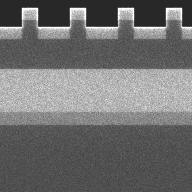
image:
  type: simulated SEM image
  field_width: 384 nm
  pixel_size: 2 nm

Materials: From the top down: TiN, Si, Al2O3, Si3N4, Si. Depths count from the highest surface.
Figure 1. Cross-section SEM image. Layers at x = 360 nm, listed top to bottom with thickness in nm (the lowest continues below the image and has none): TiN 24, Si 98, Al2O3 86, Si3N4 26, Si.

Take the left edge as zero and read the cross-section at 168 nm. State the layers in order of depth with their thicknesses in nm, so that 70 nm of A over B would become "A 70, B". TiN 24, Si 98, Al2O3 86, Si3N4 26, Si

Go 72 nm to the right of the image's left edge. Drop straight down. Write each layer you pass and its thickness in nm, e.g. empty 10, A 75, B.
TiN 24, Si 98, Al2O3 86, Si3N4 26, Si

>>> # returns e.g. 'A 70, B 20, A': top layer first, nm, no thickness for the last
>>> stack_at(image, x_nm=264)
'TiN 24, Si 98, Al2O3 86, Si3N4 26, Si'